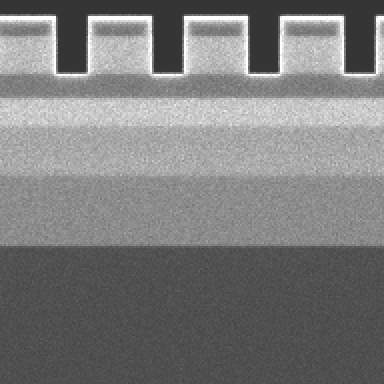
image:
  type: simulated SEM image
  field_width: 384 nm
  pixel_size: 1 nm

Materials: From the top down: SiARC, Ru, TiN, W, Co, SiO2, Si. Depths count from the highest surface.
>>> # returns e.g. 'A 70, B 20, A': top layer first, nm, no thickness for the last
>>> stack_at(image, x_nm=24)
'SiARC 20, Ru 38, TiN 24, W 28, Co 50, SiO2 70, Si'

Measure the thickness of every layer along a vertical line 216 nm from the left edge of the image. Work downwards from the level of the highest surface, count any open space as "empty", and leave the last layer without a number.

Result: SiARC 20, Ru 38, TiN 24, W 28, Co 50, SiO2 70, Si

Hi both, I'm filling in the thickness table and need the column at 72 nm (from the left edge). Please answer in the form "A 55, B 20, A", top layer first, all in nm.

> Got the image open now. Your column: empty 58, TiN 24, W 28, Co 50, SiO2 70, Si